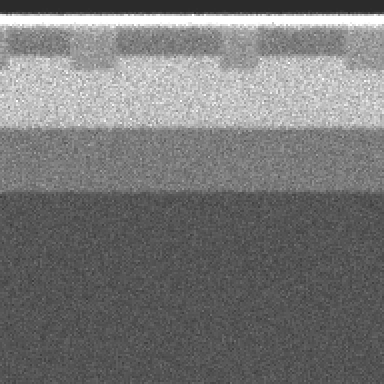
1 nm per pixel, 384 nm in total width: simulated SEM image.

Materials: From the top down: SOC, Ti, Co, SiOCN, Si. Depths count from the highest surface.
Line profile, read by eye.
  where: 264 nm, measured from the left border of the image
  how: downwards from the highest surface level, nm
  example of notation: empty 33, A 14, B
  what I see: SOC 10, Ti 30, Co 72, SiOCN 64, Si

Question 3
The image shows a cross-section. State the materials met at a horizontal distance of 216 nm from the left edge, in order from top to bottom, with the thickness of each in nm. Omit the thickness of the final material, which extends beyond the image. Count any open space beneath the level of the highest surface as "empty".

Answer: SOC 10, Ti 30, Co 72, SiOCN 64, Si